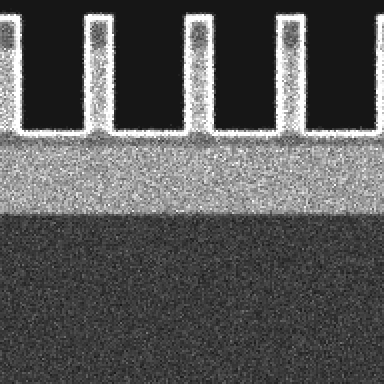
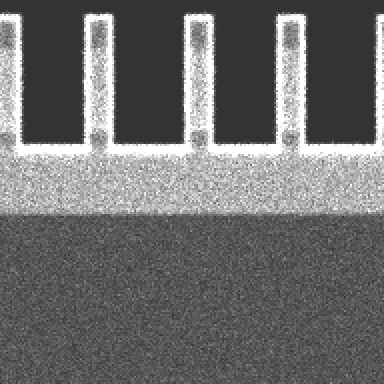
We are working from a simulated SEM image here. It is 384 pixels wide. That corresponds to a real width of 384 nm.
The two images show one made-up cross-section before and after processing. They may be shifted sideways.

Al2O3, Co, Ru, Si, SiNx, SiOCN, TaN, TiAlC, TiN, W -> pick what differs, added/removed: TiN removed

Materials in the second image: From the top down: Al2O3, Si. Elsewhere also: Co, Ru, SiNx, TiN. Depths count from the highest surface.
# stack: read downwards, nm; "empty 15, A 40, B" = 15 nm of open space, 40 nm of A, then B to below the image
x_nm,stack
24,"empty 130, Al2O3 68, Si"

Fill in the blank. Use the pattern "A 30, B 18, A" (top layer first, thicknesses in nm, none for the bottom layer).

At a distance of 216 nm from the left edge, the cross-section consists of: empty 130, Al2O3 68, Si